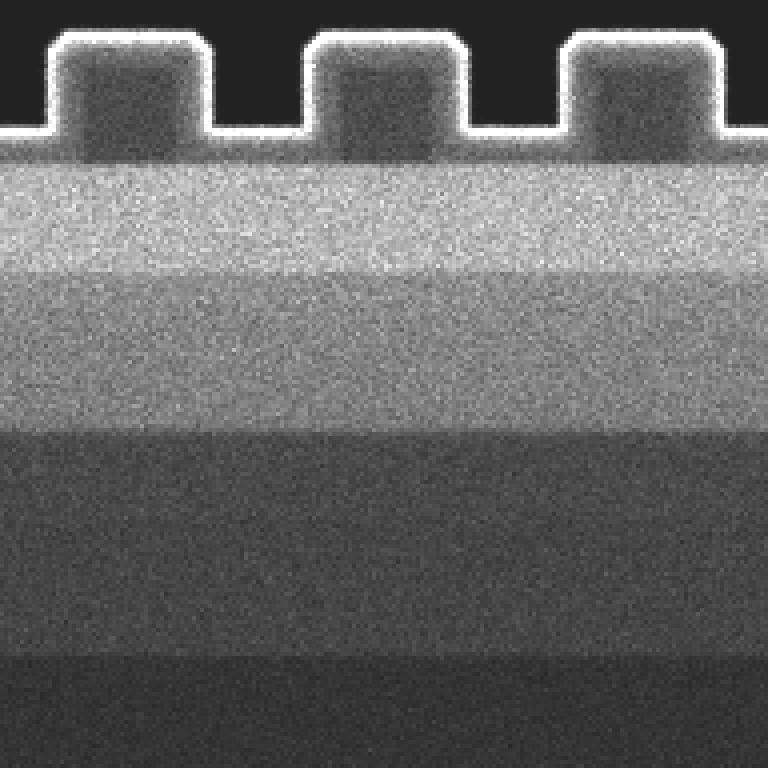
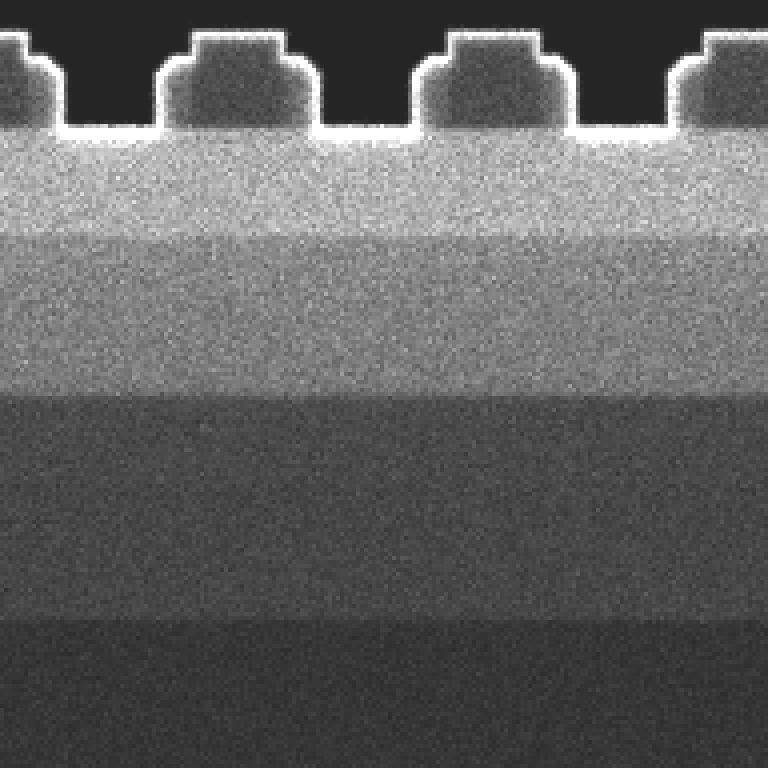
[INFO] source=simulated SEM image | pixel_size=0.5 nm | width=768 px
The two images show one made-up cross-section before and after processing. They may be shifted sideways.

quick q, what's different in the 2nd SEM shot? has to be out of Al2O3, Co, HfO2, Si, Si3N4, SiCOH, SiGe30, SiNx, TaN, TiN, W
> Al2O3 removed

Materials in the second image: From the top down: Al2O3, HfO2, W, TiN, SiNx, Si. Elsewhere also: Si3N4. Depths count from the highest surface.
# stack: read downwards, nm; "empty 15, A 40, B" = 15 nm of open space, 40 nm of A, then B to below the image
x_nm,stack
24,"empty 14, Al2O3 34, HfO2 54, W 80, TiN 44, SiNx 68, Si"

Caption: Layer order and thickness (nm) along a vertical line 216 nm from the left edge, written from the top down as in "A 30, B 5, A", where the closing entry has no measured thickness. empty 12, Al2O3 36, HfO2 54, W 80, TiN 44, SiNx 68, Si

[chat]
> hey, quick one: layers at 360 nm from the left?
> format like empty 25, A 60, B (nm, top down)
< Si3N4 48, HfO2 54, W 80, TiN 44, SiNx 68, Si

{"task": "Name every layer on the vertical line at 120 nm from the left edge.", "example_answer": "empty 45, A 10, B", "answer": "Si3N4 48, HfO2 54, W 80, TiN 44, SiNx 68, Si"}